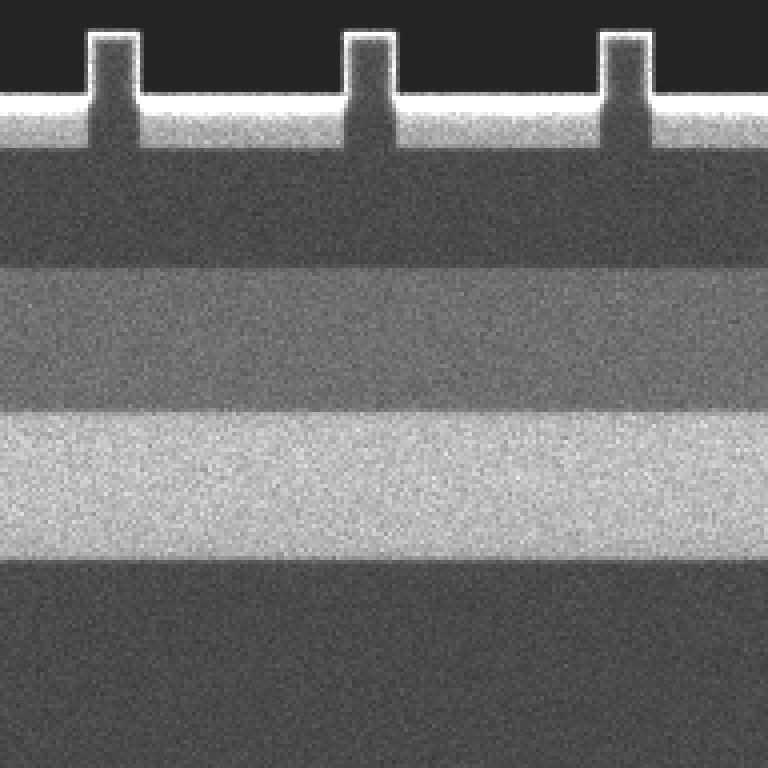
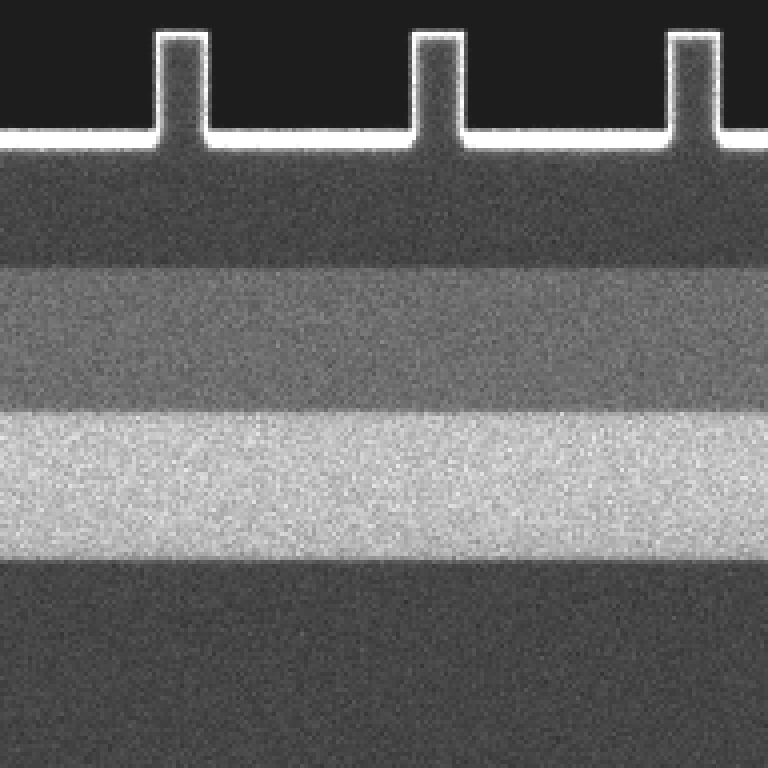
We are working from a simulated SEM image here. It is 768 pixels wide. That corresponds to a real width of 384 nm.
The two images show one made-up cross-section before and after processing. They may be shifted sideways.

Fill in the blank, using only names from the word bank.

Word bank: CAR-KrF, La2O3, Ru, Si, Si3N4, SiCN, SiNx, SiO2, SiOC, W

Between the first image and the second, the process removed SiO2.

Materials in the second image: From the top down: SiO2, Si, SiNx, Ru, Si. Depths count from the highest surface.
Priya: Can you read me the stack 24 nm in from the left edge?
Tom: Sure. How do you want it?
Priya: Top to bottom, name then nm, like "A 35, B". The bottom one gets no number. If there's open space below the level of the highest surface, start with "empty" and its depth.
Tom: empty 50, SiO2 8, Si 60, SiNx 72, Ru 74, Si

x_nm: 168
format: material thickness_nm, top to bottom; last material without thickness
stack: empty 50, SiO2 8, Si 60, SiNx 72, Ru 74, Si